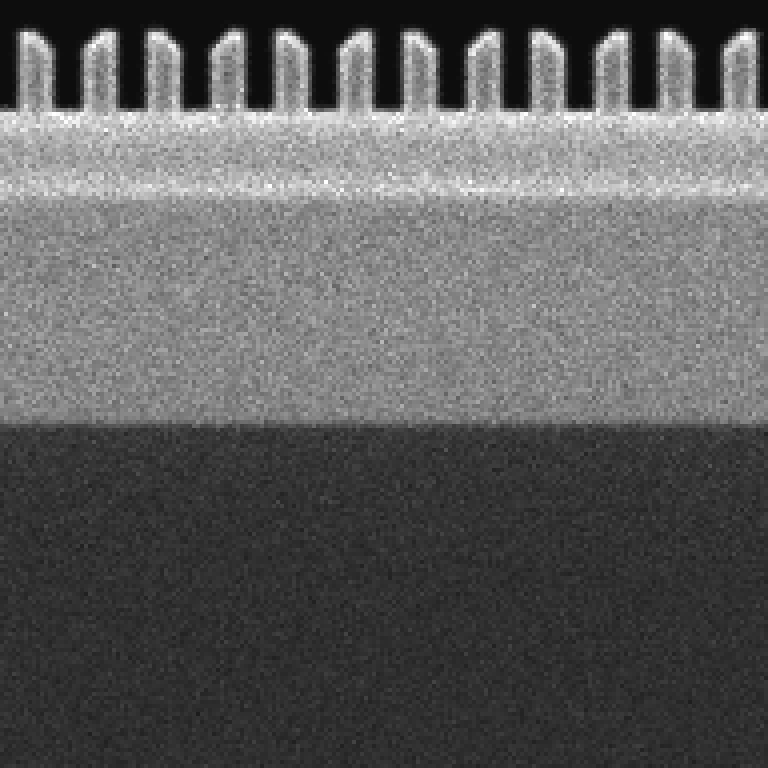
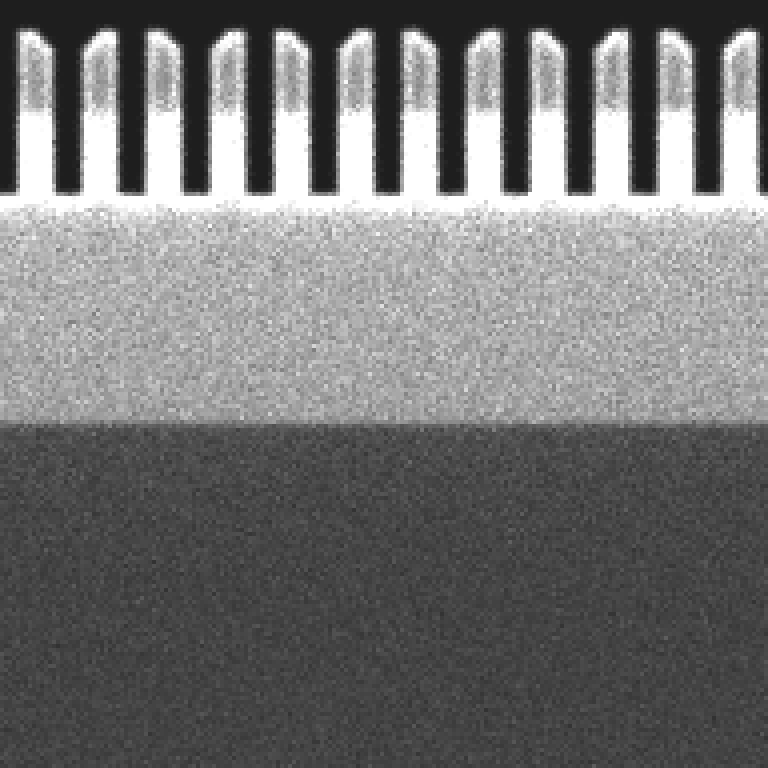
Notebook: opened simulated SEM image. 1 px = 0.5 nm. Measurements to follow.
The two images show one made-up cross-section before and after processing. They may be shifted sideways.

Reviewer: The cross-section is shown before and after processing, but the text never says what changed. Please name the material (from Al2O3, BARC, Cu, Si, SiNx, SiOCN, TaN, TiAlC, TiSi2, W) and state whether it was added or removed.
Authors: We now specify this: W, removed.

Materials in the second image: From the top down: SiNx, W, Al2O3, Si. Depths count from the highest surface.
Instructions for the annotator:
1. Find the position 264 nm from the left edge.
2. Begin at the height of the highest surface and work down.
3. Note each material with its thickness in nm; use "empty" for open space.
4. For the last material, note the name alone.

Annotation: empty 82, Al2O3 114, Si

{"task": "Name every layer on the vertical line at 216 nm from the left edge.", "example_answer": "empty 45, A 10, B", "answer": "empty 8, SiNx 32, W 42, Al2O3 114, Si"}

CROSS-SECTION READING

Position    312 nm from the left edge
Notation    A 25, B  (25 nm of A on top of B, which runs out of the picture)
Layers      SiNx 40, W 42, Al2O3 114, Si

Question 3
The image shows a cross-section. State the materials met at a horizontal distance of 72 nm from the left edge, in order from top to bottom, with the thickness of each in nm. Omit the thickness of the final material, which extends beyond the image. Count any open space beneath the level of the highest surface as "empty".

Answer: empty 82, Al2O3 114, Si